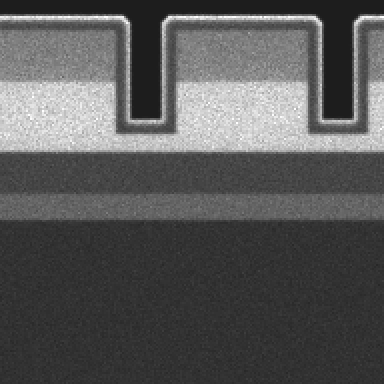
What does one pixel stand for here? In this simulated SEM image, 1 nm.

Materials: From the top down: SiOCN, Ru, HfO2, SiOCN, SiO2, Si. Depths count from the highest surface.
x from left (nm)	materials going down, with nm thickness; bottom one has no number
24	SiOCN 14, Ru 52, HfO2 70, SiOCN 42, SiO2 26, Si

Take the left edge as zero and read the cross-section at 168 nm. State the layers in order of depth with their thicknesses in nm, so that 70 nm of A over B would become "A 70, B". SiOCN 118, HfO2 18, SiOCN 42, SiO2 26, Si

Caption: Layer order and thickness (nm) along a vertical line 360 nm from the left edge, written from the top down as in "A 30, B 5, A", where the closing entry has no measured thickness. SiOCN 118, HfO2 18, SiOCN 42, SiO2 26, Si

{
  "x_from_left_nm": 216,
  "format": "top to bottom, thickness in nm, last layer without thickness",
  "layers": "SiOCN 14, Ru 52, HfO2 70, SiOCN 42, SiO2 26, Si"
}